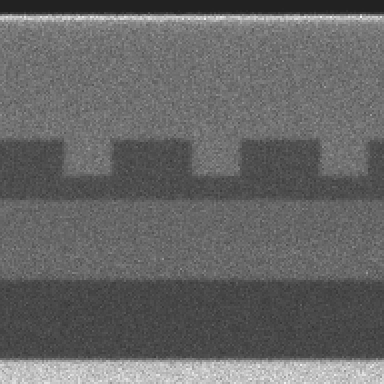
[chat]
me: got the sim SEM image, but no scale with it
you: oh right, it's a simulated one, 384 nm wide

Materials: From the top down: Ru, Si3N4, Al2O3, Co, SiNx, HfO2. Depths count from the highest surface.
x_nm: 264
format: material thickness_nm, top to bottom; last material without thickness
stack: Ru 124, Si3N4 60, Al2O3 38, Co 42, SiNx 80, HfO2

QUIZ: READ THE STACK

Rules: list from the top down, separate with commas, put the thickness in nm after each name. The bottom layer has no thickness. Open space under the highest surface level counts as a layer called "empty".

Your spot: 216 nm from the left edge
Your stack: Ru 160, Si3N4 24, Al2O3 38, Co 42, SiNx 80, HfO2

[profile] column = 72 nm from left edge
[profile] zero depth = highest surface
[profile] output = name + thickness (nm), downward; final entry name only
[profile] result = Ru 160, Si3N4 24, Al2O3 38, Co 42, SiNx 80, HfO2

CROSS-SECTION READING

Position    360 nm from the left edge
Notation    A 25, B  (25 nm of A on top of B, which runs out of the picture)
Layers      Ru 160, Si3N4 24, Al2O3 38, Co 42, SiNx 80, HfO2